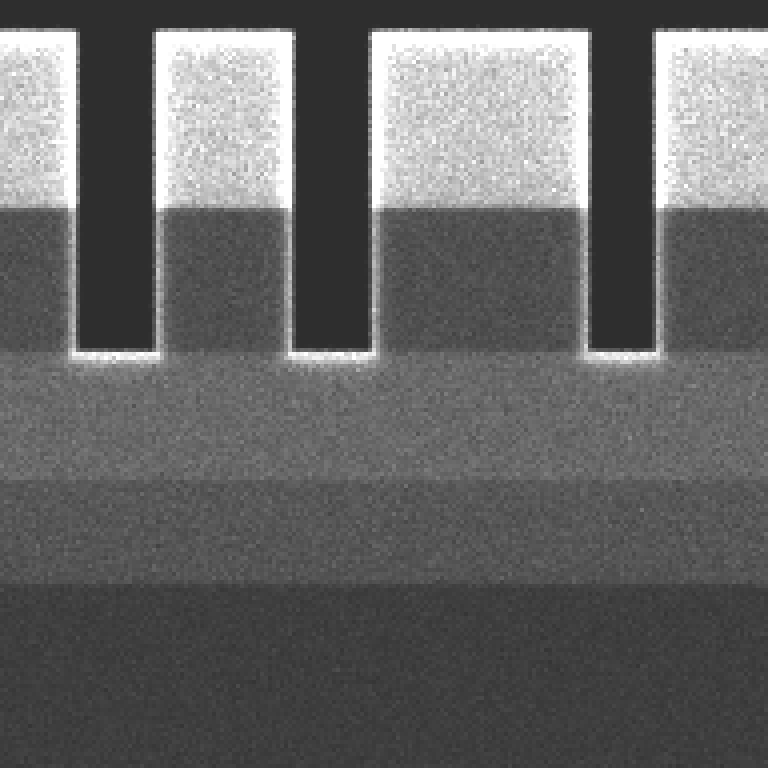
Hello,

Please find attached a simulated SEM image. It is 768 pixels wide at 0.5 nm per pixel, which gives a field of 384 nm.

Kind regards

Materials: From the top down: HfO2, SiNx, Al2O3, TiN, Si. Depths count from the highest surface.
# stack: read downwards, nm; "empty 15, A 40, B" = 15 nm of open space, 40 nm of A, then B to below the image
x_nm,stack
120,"HfO2 88, SiNx 72, Al2O3 64, TiN 52, Si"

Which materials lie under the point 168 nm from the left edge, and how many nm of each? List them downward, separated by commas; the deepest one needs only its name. empty 160, Al2O3 64, TiN 52, Si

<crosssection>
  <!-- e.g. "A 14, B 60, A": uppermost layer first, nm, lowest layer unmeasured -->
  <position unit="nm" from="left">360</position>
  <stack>HfO2 88, SiNx 72, Al2O3 64, TiN 52, Si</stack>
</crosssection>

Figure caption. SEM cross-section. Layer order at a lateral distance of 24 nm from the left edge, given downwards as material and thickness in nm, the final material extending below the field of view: HfO2 88, SiNx 72, Al2O3 64, TiN 52, Si